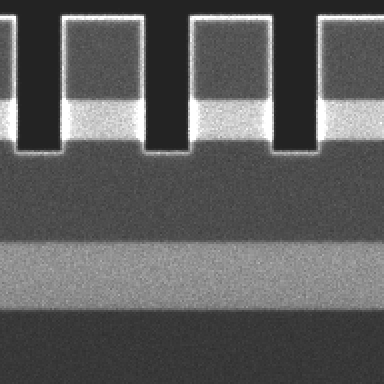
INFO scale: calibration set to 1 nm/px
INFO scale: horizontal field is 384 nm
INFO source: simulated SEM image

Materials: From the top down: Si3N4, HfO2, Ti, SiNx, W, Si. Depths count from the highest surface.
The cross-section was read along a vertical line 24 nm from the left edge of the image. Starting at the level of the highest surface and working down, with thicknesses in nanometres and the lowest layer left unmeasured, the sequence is empty 136, Ti 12, SiNx 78, W 68, Si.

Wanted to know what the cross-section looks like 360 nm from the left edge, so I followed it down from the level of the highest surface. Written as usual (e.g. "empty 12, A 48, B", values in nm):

Si3N4 84, HfO2 40, Ti 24, SiNx 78, W 68, Si